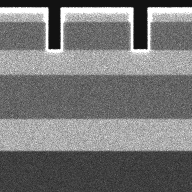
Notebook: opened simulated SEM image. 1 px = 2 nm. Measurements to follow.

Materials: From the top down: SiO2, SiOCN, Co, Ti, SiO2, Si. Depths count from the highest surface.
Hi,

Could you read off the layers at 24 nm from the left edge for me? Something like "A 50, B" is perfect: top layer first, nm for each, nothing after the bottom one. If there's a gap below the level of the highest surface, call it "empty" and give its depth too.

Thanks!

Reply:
SiO2 28, SiOCN 56, Co 50, Ti 88, SiO2 64, Si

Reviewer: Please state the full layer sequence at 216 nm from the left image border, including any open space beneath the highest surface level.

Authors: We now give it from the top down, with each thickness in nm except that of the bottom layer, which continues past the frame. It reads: SiO2 28, SiOCN 56, Co 50, Ti 88, SiO2 64, Si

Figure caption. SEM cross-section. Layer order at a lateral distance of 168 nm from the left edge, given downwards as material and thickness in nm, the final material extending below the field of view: SiO2 28, SiOCN 56, Co 50, Ti 88, SiO2 64, Si